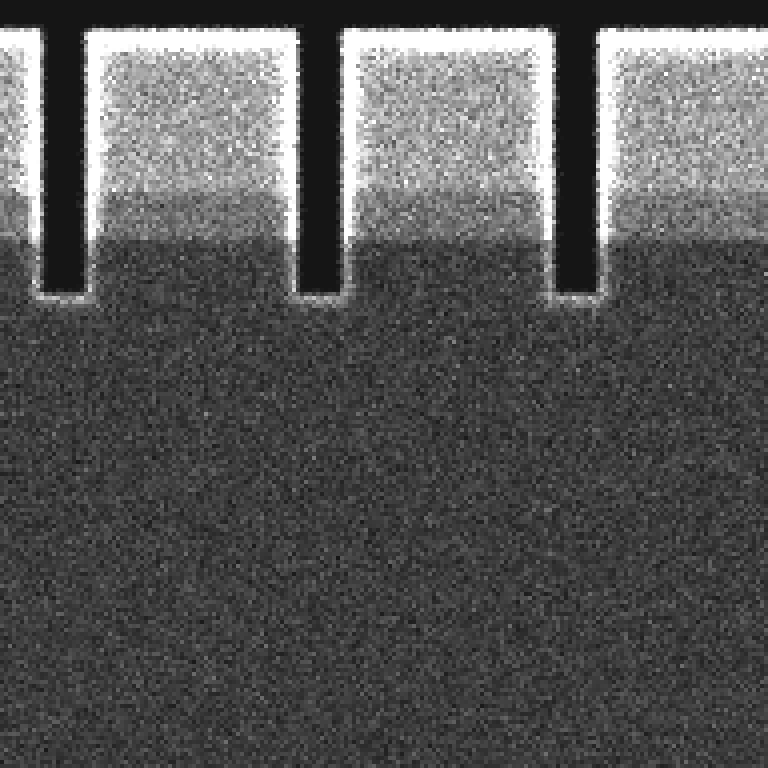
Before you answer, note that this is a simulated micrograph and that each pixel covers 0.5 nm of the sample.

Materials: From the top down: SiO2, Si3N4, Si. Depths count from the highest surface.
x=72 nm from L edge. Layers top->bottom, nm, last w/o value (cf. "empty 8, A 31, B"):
SiO2 80, Si3N4 24, Si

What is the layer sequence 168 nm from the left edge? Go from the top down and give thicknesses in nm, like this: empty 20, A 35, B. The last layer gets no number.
empty 132, Si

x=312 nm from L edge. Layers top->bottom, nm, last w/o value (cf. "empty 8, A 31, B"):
SiO2 80, Si3N4 24, Si